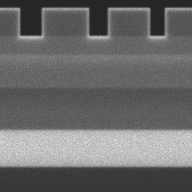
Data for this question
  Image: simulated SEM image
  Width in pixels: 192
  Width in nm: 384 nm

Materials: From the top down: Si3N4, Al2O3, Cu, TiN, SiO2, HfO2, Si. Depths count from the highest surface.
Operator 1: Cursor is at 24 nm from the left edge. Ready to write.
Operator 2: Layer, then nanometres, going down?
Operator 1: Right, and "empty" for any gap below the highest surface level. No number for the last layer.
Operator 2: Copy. Si3N4 56, Al2O3 38, Cu 66, TiN 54, SiO2 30, HfO2 74, Si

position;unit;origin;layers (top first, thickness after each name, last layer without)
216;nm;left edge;Si3N4 56, Al2O3 38, Cu 66, TiN 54, SiO2 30, HfO2 74, Si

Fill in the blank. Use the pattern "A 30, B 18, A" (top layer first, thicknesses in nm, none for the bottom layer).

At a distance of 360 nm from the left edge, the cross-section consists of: Si3N4 56, Al2O3 38, Cu 66, TiN 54, SiO2 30, HfO2 74, Si